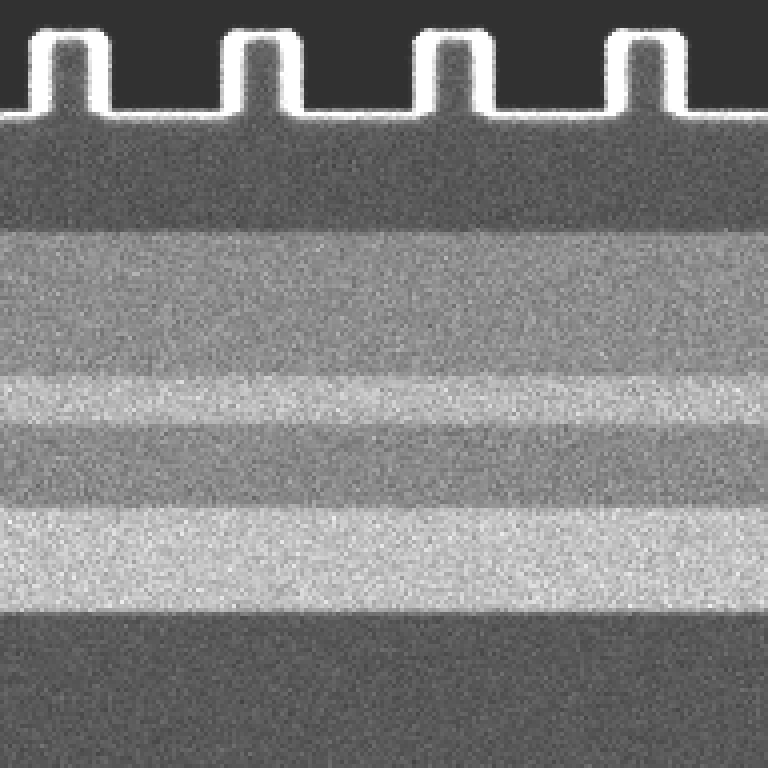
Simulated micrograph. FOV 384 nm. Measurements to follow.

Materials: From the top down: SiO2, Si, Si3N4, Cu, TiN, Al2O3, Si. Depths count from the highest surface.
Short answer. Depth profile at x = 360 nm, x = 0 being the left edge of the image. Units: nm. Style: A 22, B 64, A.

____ empty 40, Si 60, Si3N4 72, Cu 24, TiN 42, Al2O3 52, Si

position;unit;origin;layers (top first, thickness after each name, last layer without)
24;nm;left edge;SiO2 40, Si 60, Si3N4 72, Cu 24, TiN 42, Al2O3 52, Si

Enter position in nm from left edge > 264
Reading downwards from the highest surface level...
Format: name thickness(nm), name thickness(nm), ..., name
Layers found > empty 40, Si 60, Si3N4 72, Cu 24, TiN 42, Al2O3 52, Si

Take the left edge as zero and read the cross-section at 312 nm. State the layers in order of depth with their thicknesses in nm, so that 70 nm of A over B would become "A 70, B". SiO2 40, Si 60, Si3N4 72, Cu 24, TiN 42, Al2O3 52, Si